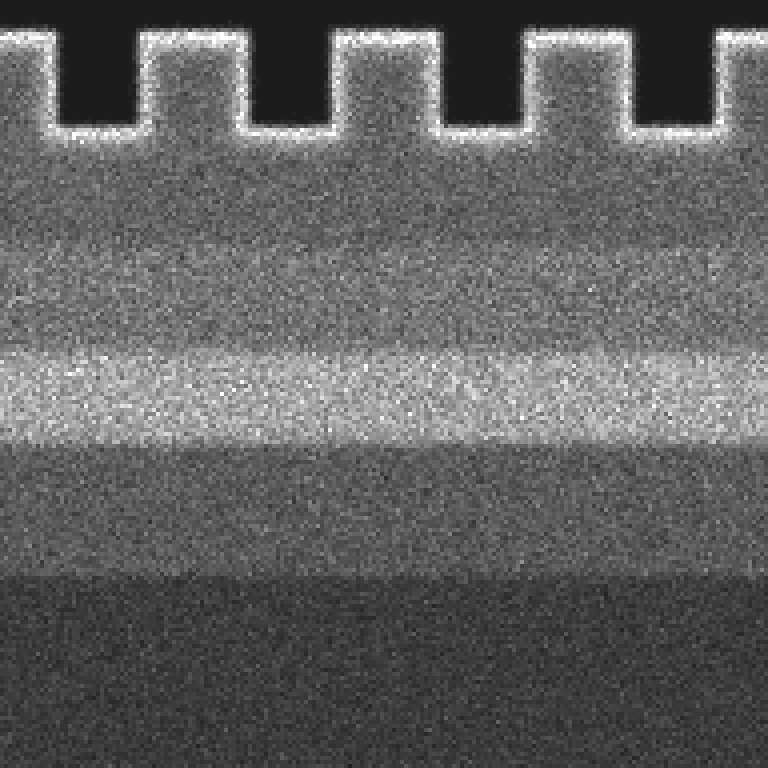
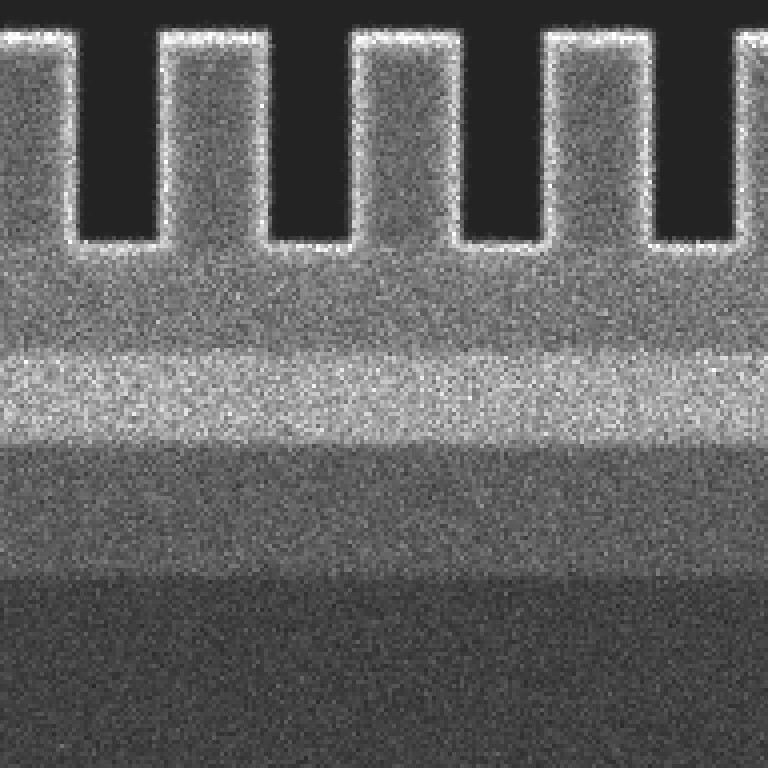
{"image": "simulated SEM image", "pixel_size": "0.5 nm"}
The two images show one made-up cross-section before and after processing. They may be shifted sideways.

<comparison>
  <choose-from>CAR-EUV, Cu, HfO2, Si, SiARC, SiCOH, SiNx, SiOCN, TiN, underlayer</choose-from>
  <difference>underlayer removed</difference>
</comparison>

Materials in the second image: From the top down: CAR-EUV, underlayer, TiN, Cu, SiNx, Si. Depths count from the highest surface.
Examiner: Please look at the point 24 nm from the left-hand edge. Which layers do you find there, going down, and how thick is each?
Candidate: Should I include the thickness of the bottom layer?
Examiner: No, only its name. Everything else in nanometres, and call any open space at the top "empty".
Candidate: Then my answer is CAR-EUV 48, underlayer 58, TiN 54, Cu 46, SiNx 66, Si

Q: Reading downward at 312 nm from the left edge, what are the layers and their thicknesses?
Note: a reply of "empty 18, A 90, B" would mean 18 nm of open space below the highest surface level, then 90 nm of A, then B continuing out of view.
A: CAR-EUV 48, underlayer 58, TiN 54, Cu 46, SiNx 66, Si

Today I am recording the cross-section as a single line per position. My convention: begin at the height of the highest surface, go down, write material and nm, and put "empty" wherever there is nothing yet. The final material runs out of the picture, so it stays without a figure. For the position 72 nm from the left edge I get empty 106, TiN 54, Cu 46, SiNx 66, Si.